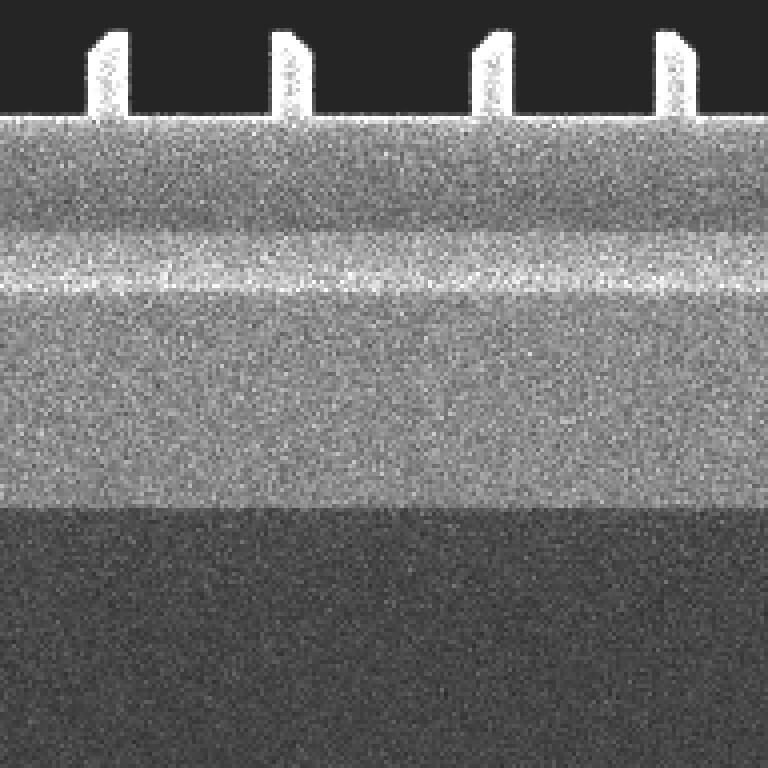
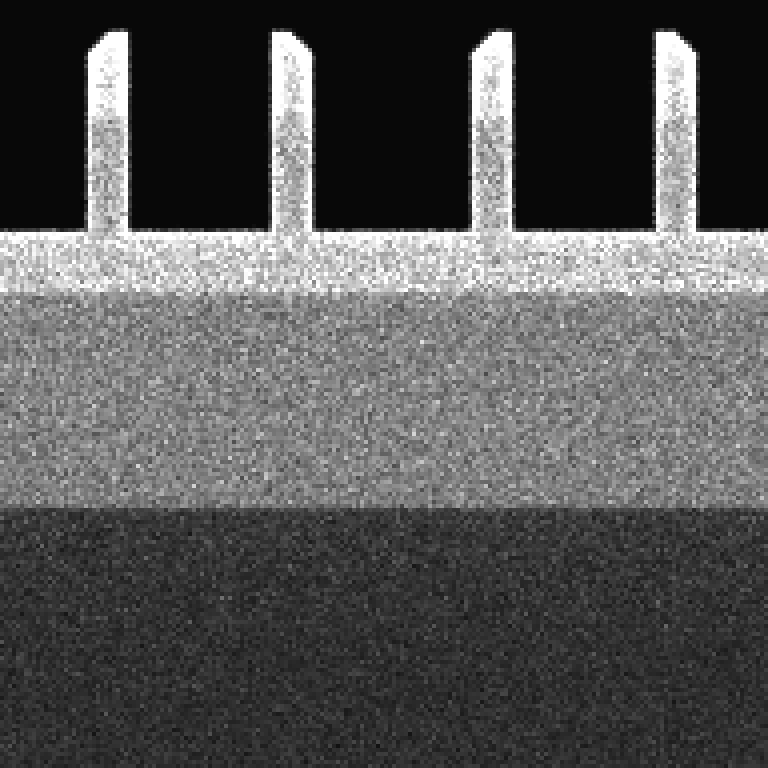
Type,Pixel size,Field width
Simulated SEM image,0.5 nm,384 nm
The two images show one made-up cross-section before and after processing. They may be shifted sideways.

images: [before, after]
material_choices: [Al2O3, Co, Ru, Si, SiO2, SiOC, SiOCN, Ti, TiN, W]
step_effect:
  removed: TiN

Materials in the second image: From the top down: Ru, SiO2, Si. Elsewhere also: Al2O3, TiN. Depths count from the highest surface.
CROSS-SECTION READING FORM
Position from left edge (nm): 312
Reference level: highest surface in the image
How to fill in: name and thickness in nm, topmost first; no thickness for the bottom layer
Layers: empty 100, Ru 30, SiO2 108, Si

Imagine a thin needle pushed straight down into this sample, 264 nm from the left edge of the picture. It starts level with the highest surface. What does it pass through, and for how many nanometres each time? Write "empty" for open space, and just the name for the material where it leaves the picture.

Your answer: empty 100, Ru 30, SiO2 108, Si